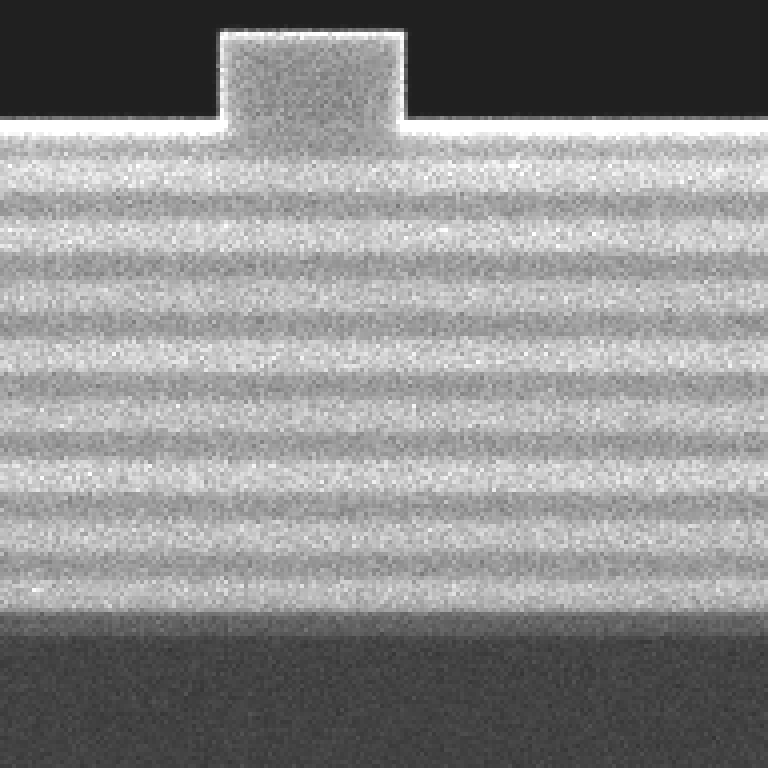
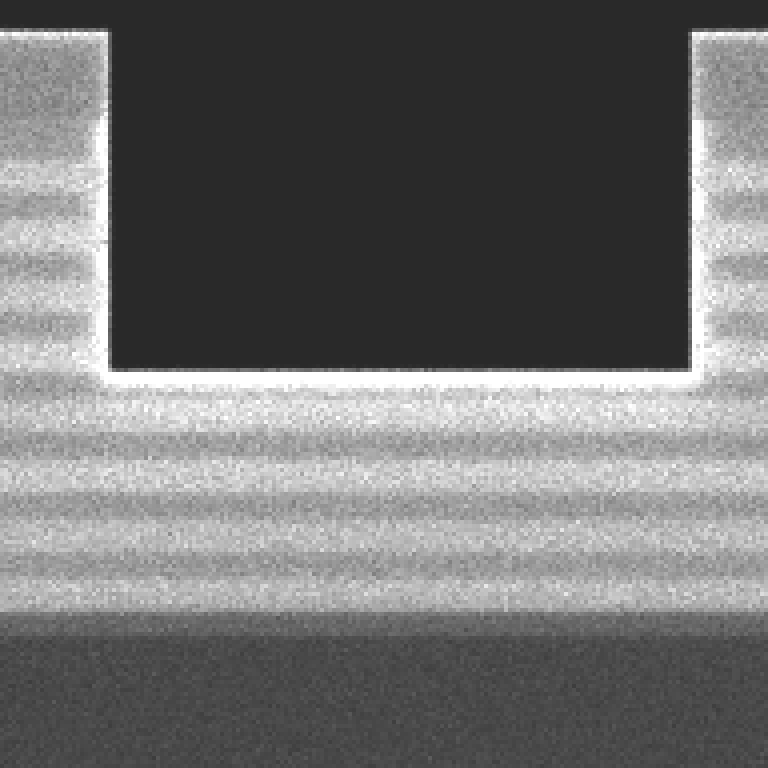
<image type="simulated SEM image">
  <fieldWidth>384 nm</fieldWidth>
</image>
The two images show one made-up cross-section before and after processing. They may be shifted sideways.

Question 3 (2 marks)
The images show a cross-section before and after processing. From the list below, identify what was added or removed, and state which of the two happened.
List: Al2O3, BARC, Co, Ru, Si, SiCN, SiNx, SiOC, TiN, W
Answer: Al2O3 and Co and Ru was removed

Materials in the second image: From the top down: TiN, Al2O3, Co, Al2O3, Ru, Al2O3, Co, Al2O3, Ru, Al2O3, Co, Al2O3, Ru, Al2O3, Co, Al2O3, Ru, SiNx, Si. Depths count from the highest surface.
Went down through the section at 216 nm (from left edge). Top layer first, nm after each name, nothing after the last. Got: empty 170, Al2O3 14, Co 16, Al2O3 14, Ru 16, Al2O3 14, Co 16, Al2O3 14, Ru 16, SiNx 12, Si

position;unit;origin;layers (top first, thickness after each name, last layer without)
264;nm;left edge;empty 170, Al2O3 14, Co 16, Al2O3 14, Ru 16, Al2O3 14, Co 16, Al2O3 14, Ru 16, SiNx 12, Si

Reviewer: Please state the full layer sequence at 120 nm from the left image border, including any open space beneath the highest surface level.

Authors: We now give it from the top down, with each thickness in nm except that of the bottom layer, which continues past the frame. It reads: empty 170, Al2O3 14, Co 16, Al2O3 14, Ru 16, Al2O3 14, Co 16, Al2O3 14, Ru 16, SiNx 12, Si